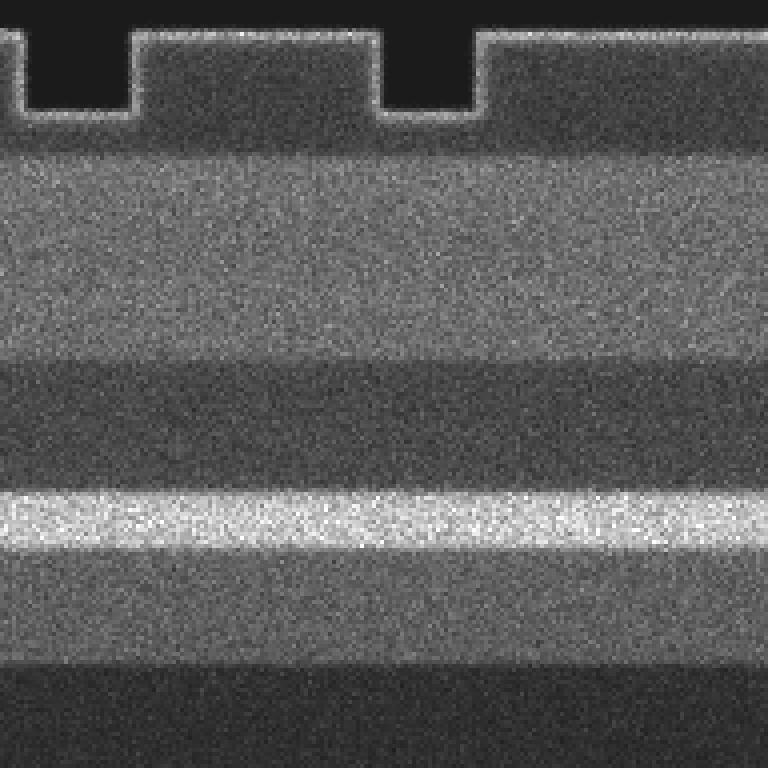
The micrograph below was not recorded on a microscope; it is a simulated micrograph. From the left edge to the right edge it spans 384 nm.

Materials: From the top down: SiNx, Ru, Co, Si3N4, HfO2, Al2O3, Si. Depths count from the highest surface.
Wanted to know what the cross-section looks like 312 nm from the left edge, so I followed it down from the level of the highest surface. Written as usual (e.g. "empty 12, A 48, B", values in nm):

SiNx 62, Ru 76, Co 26, Si3N4 66, HfO2 28, Al2O3 58, Si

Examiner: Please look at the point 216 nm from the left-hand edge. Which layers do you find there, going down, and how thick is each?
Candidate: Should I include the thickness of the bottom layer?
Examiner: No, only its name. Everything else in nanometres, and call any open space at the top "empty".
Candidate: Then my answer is empty 40, SiNx 22, Ru 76, Co 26, Si3N4 66, HfO2 28, Al2O3 58, Si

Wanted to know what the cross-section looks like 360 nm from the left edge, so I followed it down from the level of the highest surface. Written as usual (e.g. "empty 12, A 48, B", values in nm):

SiNx 62, Ru 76, Co 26, Si3N4 66, HfO2 28, Al2O3 58, Si